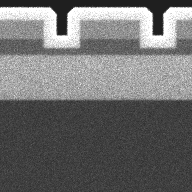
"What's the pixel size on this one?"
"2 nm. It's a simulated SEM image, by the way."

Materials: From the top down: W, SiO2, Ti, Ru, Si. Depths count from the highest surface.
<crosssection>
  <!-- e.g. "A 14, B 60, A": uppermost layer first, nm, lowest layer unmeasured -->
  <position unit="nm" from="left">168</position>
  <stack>W 24, SiO2 38, Ti 32, Ru 90, Si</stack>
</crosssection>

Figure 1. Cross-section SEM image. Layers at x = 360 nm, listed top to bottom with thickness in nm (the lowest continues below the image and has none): W 24, SiO2 38, Ti 32, Ru 90, Si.